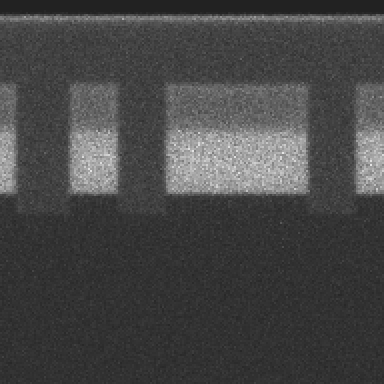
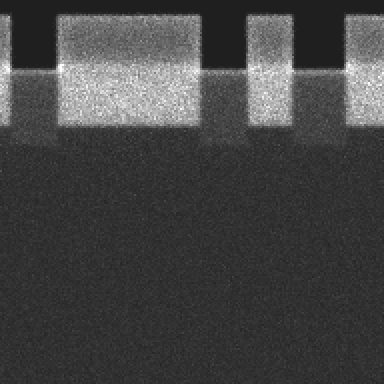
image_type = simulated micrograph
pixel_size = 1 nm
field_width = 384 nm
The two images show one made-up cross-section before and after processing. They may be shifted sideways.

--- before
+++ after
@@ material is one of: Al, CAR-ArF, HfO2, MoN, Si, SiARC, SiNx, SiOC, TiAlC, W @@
SiNx removed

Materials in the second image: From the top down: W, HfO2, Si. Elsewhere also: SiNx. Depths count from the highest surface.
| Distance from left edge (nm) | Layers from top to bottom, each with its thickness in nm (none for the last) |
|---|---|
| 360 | W 48, HfO2 62, Si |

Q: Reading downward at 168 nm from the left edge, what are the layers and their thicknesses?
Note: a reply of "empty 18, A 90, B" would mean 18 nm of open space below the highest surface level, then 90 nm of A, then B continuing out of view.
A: W 48, HfO2 62, Si